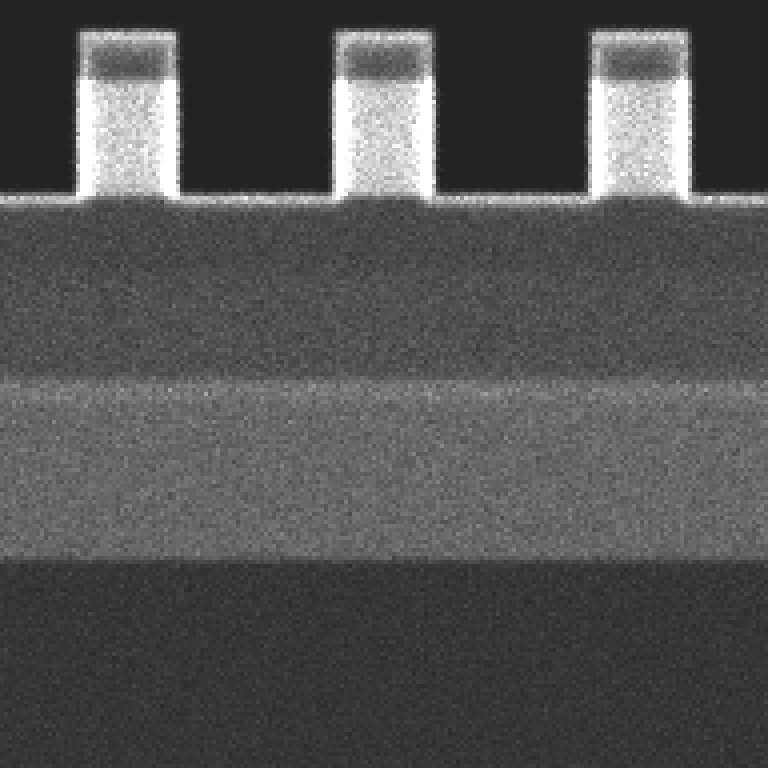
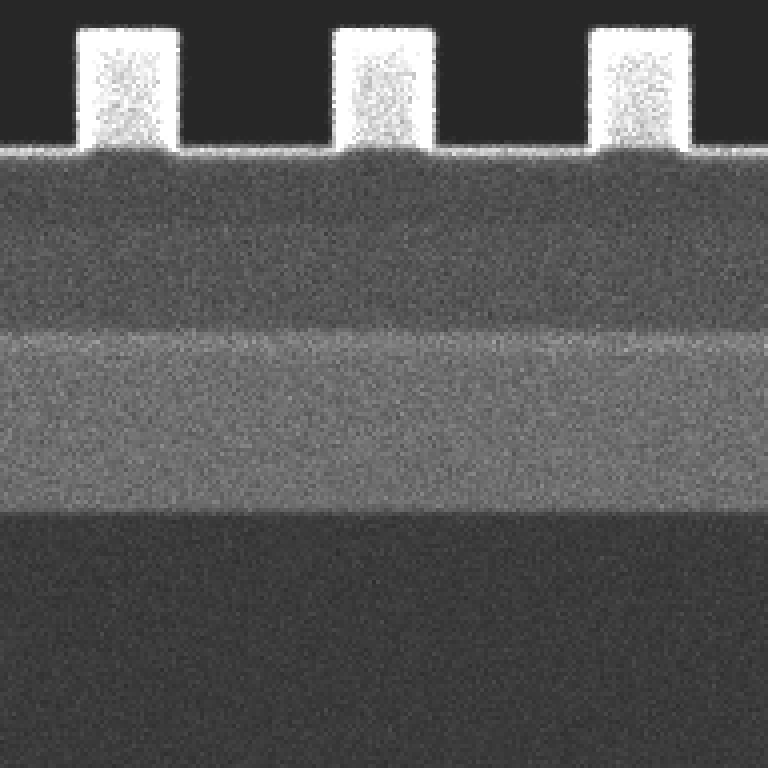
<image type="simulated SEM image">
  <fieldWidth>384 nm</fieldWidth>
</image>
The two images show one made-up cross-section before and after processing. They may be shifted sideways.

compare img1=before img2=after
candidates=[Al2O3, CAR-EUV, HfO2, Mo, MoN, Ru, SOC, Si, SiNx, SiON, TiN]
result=removed:SOC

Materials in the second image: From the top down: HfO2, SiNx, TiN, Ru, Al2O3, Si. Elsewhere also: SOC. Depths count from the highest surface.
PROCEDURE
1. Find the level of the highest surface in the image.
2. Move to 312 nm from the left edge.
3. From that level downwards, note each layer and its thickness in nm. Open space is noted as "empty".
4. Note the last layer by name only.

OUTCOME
HfO2 58, SiNx 38, TiN 54, Ru 10, Al2O3 80, Si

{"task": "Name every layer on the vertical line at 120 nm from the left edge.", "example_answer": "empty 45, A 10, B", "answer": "empty 58, SiNx 38, TiN 54, Ru 10, Al2O3 80, Si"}